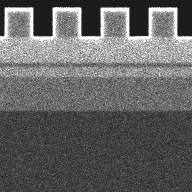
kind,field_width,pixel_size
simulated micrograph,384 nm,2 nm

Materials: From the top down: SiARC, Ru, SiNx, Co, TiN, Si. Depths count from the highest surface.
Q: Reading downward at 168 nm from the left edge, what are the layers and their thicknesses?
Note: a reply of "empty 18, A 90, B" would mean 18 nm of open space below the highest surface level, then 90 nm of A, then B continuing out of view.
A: empty 58, Ru 52, SiNx 8, Co 20, TiN 68, Si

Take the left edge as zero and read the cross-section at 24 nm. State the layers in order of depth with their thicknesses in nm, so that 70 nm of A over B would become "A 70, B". SiARC 58, Ru 52, SiNx 8, Co 20, TiN 68, Si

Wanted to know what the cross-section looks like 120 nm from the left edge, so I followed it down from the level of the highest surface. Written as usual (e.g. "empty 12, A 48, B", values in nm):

SiARC 58, Ru 52, SiNx 8, Co 20, TiN 68, Si